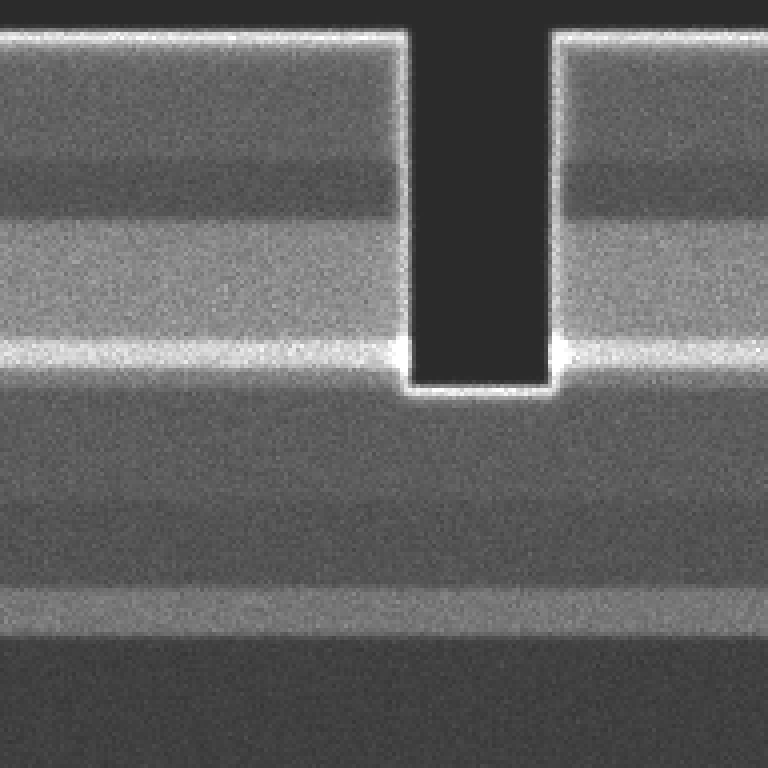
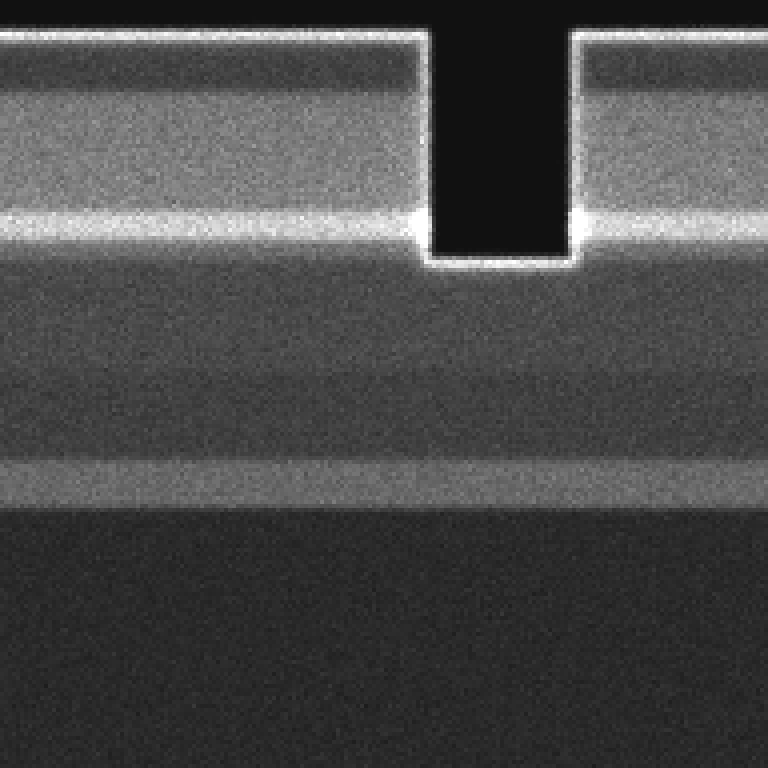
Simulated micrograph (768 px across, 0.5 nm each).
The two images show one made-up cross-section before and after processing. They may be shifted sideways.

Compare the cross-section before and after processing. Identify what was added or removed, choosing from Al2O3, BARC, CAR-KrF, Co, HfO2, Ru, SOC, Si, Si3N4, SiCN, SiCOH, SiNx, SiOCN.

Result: SOC removed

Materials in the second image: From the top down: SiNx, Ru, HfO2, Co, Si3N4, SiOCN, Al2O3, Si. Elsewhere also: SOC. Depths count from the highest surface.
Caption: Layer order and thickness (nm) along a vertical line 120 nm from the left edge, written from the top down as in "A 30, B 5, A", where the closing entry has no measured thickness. SiNx 30, Ru 60, HfO2 14, Co 10, Si3N4 56, SiOCN 44, Al2O3 24, Si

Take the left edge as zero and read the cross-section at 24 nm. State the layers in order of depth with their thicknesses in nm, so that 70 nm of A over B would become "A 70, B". SiNx 30, Ru 60, HfO2 14, Co 10, Si3N4 56, SiOCN 44, Al2O3 24, Si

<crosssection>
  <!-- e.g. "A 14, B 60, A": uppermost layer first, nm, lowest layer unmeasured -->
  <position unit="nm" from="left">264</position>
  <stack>empty 114, Si3N4 56, SiOCN 44, Al2O3 24, Si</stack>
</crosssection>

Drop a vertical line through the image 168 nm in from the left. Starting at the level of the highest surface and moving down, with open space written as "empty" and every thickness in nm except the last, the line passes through SiNx 30, Ru 60, HfO2 14, Co 10, Si3N4 56, SiOCN 44, Al2O3 24, Si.